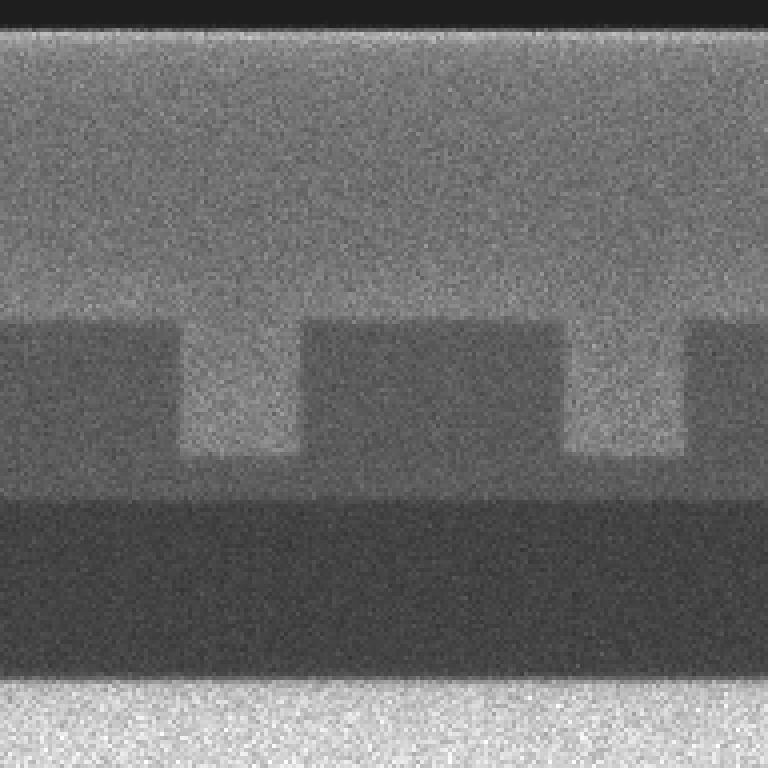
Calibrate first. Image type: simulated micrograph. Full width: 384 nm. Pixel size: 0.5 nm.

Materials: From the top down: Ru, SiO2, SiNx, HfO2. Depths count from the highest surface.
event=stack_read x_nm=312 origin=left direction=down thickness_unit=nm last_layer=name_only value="Ru 212, SiO2 22, SiNx 90, HfO2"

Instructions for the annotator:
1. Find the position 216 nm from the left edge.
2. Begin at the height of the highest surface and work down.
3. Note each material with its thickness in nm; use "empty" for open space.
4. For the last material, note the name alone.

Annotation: Ru 144, SiO2 90, SiNx 90, HfO2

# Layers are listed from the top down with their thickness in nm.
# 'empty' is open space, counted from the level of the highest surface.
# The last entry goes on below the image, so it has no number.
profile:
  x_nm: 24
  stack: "Ru 144, SiO2 90, SiNx 90, HfO2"